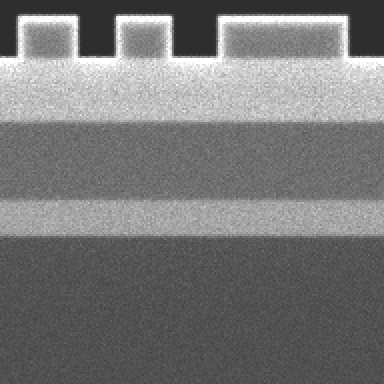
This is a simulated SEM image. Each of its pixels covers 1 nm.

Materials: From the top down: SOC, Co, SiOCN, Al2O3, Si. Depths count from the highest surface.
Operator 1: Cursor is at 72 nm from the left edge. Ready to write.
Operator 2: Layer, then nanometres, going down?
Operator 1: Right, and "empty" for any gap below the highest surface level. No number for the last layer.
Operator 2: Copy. SOC 42, Co 64, SiOCN 78, Al2O3 36, Si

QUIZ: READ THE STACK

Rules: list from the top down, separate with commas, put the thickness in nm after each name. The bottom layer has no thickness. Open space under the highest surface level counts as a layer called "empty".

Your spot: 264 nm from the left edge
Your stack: SOC 42, Co 64, SiOCN 78, Al2O3 36, Si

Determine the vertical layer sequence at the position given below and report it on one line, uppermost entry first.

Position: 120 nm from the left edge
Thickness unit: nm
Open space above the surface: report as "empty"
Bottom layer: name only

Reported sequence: SOC 42, Co 64, SiOCN 78, Al2O3 36, Si